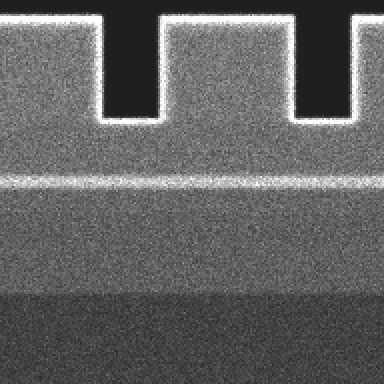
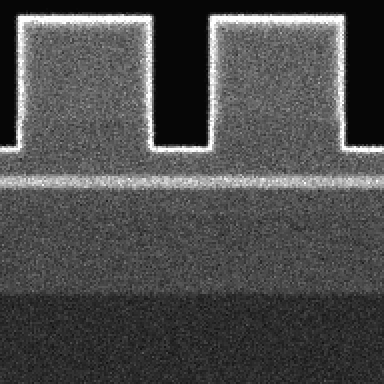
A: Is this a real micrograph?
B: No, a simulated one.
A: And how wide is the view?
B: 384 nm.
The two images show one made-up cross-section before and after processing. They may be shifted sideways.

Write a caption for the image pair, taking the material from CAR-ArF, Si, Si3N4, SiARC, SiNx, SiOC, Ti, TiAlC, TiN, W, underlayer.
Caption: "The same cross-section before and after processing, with TiN removed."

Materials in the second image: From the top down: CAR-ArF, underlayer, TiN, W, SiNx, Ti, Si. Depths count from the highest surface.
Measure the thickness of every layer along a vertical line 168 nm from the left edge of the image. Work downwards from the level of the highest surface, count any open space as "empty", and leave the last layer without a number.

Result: empty 132, TiN 28, W 12, SiNx 26, Ti 80, Si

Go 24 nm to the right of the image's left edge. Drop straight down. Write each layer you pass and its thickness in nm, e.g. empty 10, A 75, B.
CAR-ArF 76, underlayer 28, TiN 56, W 12, SiNx 26, Ti 80, Si